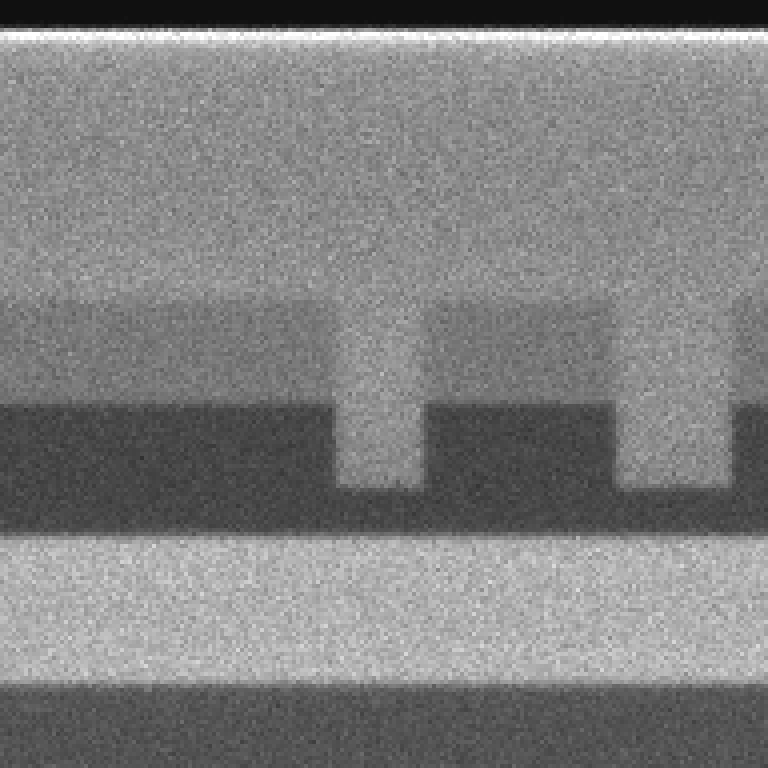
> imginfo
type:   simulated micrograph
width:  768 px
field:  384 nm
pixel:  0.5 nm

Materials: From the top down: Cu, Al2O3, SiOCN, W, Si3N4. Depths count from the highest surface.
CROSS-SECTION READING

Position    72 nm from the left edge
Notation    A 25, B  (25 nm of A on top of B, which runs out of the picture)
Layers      Cu 134, Al2O3 52, SiOCN 66, W 74, Si3N4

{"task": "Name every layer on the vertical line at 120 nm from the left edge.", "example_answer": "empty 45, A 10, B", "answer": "Cu 134, Al2O3 52, SiOCN 66, W 74, Si3N4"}